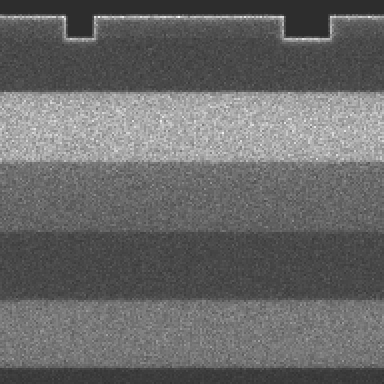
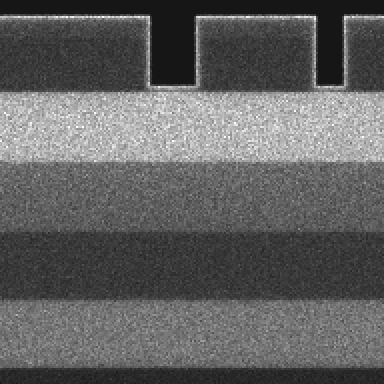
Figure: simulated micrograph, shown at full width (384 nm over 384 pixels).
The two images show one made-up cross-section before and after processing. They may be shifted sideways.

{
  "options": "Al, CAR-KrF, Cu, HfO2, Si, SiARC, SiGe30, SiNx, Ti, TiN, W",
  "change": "removed",
  "material": "SiNx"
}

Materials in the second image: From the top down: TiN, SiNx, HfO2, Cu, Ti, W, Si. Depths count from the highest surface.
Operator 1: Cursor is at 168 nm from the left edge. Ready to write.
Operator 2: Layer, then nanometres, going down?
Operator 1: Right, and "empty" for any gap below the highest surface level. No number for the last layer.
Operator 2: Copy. empty 70, SiNx 6, HfO2 70, Cu 70, Ti 68, W 68, Si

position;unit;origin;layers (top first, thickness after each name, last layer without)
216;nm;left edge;TiN 22, SiNx 54, HfO2 70, Cu 70, Ti 68, W 68, Si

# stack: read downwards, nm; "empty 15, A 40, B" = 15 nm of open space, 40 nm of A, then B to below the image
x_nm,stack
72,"TiN 22, SiNx 54, HfO2 70, Cu 70, Ti 68, W 68, Si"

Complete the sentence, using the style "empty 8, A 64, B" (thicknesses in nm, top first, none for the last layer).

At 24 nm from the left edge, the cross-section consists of TiN 22, SiNx 54, HfO2 70, Cu 70, Ti 68, W 68, Si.